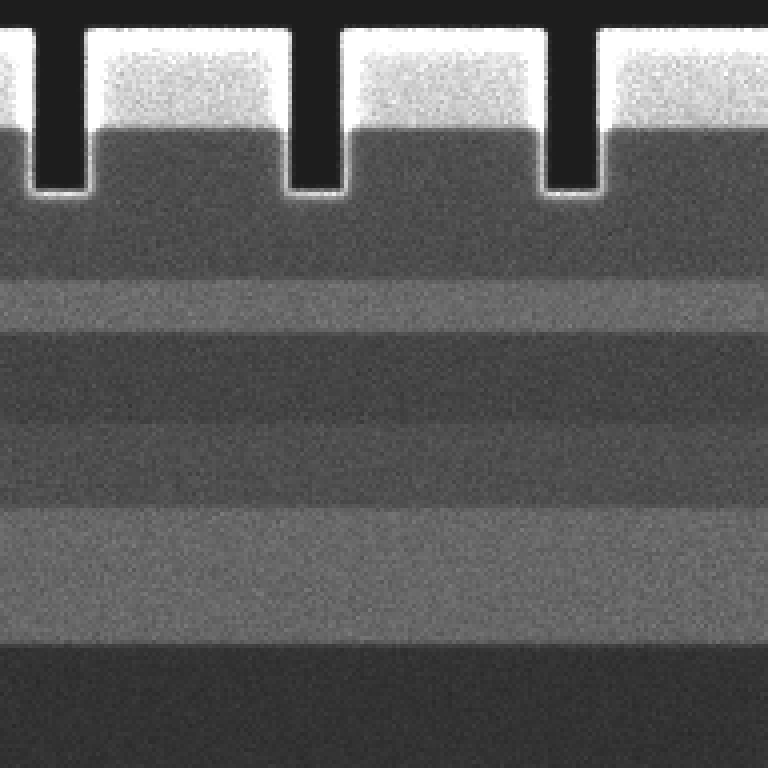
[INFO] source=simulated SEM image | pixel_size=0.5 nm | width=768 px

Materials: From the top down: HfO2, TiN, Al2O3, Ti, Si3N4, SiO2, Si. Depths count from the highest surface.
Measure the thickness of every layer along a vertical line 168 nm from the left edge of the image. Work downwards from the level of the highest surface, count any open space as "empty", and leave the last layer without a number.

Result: empty 80, TiN 44, Al2O3 26, Ti 46, Si3N4 42, SiO2 68, Si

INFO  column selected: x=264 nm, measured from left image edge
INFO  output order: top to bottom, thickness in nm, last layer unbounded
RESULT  HfO2 48, TiN 76, Al2O3 26, Ti 46, Si3N4 42, SiO2 68, Si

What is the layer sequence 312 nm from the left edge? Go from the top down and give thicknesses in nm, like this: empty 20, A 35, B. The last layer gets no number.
HfO2 48, TiN 76, Al2O3 26, Ti 46, Si3N4 42, SiO2 68, Si